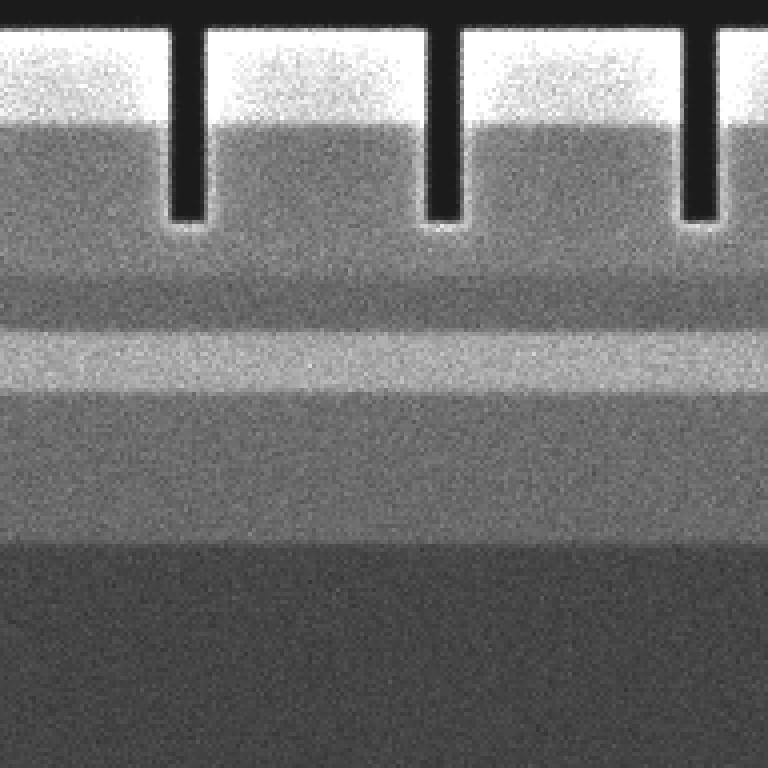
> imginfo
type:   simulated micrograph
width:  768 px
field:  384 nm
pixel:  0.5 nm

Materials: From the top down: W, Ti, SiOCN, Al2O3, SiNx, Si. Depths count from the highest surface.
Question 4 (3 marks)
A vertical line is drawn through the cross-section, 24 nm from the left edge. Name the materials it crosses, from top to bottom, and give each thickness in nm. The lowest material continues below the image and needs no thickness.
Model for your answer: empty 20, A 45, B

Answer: W 46, Ti 76, SiOCN 28, Al2O3 30, SiNx 76, Si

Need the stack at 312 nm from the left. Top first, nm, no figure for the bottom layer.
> W 46, Ti 76, SiOCN 28, Al2O3 30, SiNx 76, Si